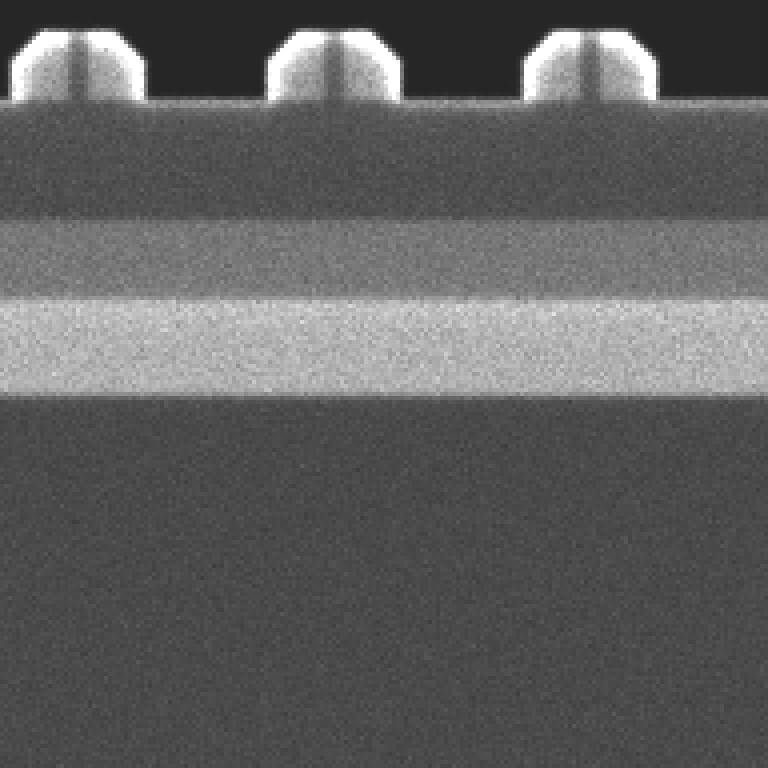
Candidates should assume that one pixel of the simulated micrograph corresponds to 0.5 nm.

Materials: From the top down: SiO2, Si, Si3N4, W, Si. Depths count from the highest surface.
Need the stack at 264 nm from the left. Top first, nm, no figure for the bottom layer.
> empty 12, SiO2 22, Si 60, Si3N4 40, W 48, Si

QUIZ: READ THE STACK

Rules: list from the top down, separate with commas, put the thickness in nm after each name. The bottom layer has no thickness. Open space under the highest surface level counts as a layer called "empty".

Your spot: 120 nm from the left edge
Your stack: empty 34, Si 60, Si3N4 40, W 48, Si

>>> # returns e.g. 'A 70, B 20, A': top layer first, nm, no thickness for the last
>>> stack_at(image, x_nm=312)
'SiO2 34, Si 60, Si3N4 40, W 48, Si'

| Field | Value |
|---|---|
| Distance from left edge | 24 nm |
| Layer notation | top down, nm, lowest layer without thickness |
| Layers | SiO2 34, Si 60, Si3N4 40, W 48, Si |